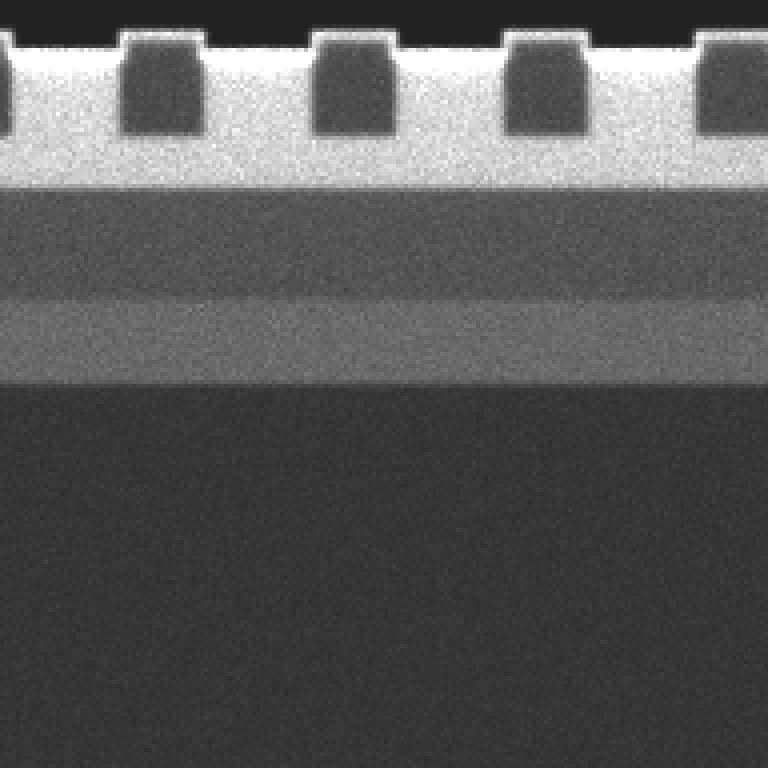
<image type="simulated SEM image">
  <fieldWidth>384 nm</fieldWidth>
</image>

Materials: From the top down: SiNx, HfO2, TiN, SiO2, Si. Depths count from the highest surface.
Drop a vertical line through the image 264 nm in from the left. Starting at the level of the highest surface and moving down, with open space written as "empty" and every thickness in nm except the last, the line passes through SiNx 52, HfO2 26, TiN 56, SiO2 42, Si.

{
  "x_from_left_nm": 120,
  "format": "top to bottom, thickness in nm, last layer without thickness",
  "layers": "empty 10, HfO2 68, TiN 56, SiO2 42, Si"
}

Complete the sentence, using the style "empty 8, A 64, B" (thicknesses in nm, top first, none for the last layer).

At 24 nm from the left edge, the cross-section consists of empty 10, HfO2 68, TiN 56, SiO2 42, Si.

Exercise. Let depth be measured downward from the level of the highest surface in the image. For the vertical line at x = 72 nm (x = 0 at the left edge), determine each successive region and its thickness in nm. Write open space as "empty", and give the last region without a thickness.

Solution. SiNx 52, HfO2 26, TiN 56, SiO2 42, Si